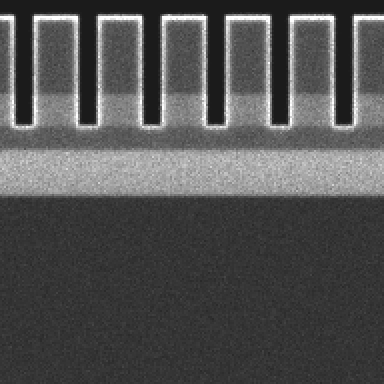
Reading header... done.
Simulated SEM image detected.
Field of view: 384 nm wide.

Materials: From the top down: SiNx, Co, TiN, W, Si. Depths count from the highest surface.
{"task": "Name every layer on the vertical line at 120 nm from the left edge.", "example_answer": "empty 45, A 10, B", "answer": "SiNx 78, Co 32, TiN 24, W 46, Si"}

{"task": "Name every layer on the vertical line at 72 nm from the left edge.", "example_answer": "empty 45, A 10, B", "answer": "SiNx 78, Co 32, TiN 24, W 46, Si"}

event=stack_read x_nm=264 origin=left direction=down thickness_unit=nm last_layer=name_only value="SiNx 78, Co 32, TiN 24, W 46, Si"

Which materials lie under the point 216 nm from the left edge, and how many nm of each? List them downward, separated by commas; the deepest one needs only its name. empty 110, TiN 24, W 46, Si